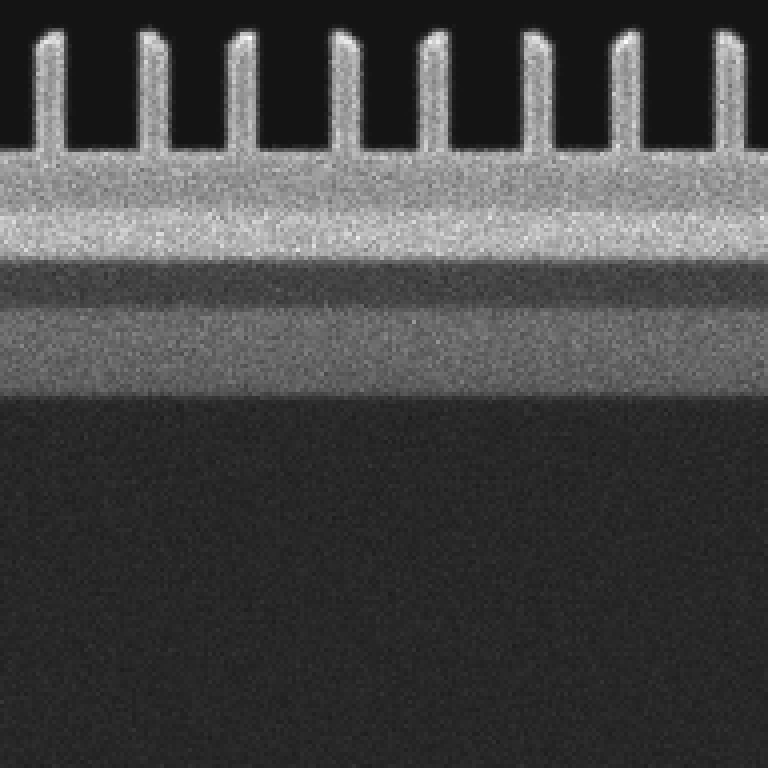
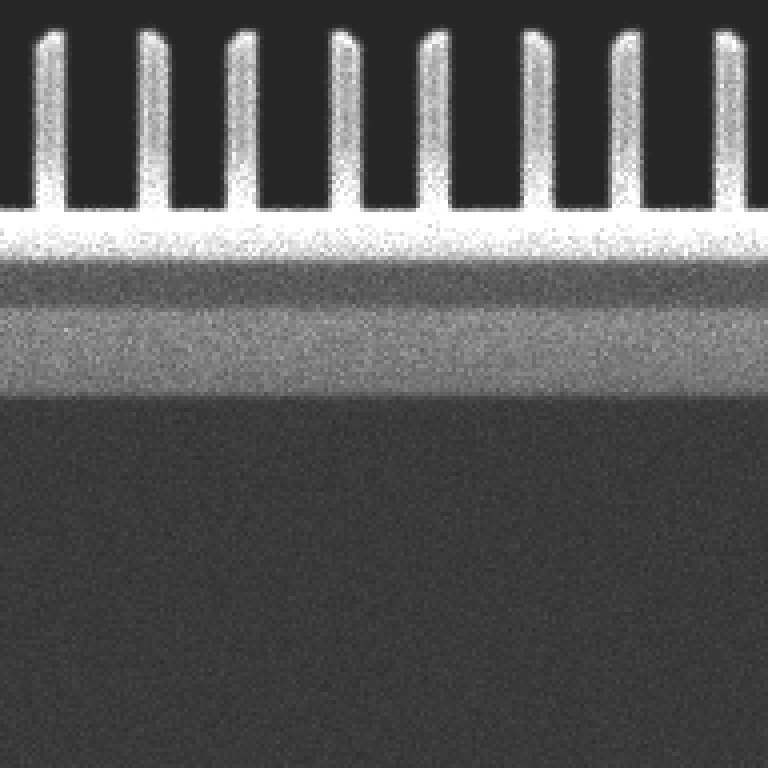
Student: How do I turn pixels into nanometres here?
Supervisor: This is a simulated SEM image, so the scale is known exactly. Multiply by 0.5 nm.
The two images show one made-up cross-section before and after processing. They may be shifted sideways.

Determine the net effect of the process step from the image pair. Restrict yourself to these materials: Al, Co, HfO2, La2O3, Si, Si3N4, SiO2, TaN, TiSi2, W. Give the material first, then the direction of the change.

W: removed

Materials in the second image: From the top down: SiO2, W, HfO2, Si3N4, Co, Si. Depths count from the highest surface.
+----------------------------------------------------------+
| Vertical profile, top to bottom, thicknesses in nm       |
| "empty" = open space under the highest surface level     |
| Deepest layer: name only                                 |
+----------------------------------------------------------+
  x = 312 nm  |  SiO2 60, W 30, HfO2 24, Si3N4 24, Co 44, Si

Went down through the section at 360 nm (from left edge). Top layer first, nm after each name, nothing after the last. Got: SiO2 60, W 30, HfO2 24, Si3N4 24, Co 44, Si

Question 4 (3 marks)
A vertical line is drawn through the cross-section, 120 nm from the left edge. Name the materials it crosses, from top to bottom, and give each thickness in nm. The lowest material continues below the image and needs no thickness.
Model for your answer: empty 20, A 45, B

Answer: SiO2 60, W 30, HfO2 24, Si3N4 24, Co 44, Si